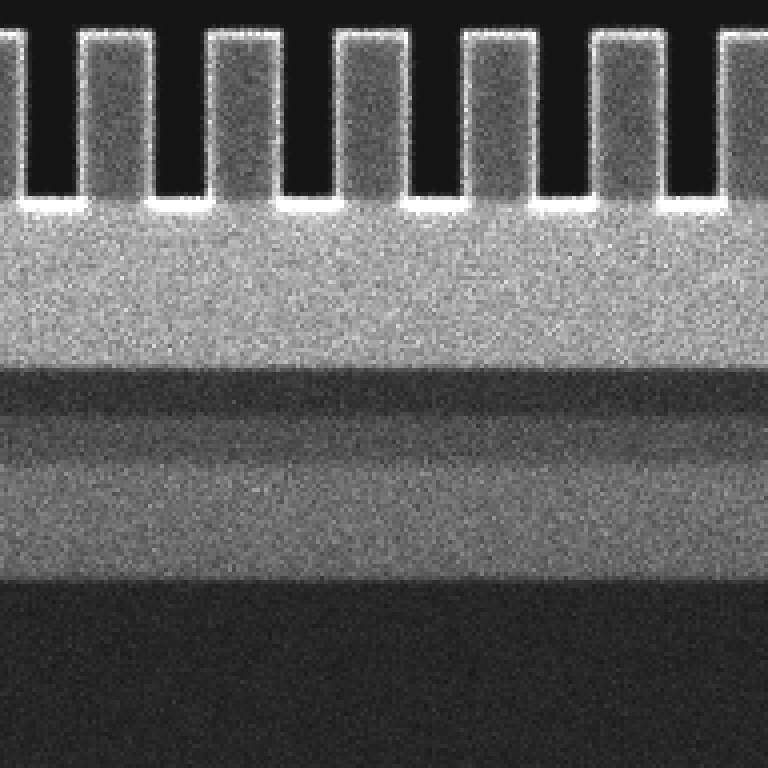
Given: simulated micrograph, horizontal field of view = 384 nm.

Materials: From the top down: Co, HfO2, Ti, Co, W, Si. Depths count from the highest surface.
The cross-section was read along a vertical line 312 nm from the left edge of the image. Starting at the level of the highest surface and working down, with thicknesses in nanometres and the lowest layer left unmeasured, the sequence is Co 84, HfO2 84, Ti 24, Co 24, W 58, Si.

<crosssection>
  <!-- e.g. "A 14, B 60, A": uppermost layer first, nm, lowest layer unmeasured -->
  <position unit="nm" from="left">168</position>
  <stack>Co 84, HfO2 84, Ti 24, Co 24, W 58, Si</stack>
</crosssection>